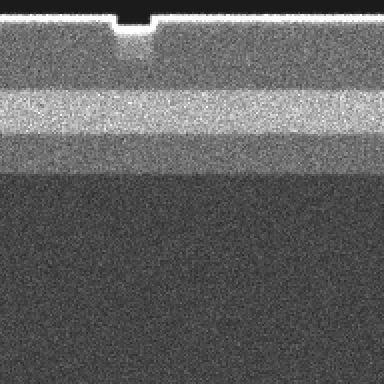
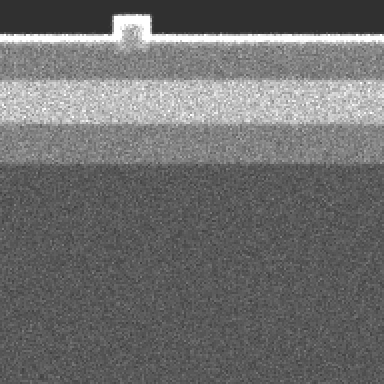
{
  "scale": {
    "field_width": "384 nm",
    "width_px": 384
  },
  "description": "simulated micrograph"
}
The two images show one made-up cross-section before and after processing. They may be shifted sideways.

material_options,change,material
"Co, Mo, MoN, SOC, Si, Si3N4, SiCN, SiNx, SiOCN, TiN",removed,SiOCN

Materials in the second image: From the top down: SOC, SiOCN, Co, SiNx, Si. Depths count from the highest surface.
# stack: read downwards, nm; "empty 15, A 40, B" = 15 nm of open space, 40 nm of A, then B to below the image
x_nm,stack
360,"empty 20, SiOCN 44, Co 44, SiNx 40, Si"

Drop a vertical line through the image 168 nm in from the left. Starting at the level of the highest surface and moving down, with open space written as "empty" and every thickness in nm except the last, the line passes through empty 20, SiOCN 44, Co 44, SiNx 40, Si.